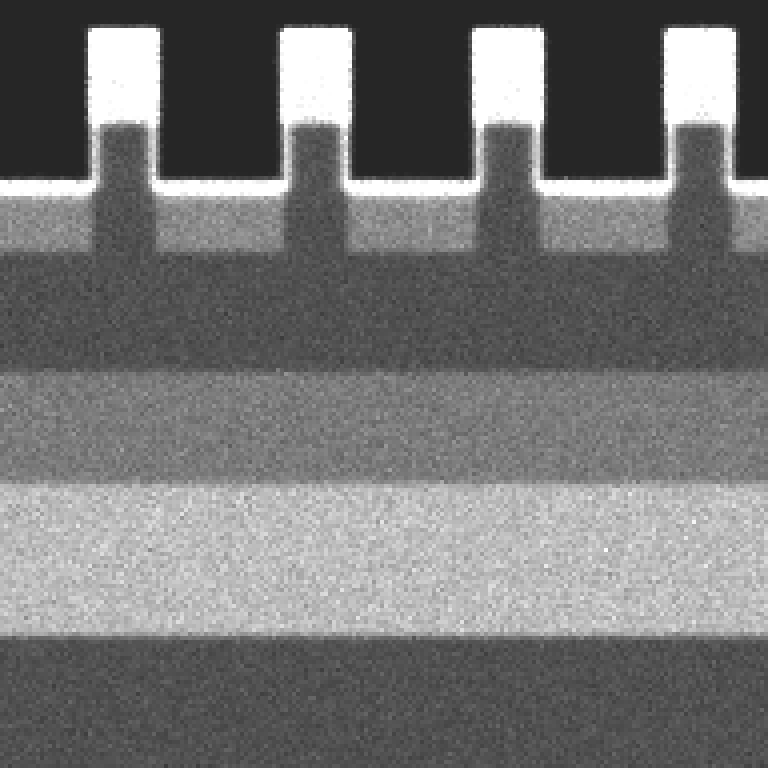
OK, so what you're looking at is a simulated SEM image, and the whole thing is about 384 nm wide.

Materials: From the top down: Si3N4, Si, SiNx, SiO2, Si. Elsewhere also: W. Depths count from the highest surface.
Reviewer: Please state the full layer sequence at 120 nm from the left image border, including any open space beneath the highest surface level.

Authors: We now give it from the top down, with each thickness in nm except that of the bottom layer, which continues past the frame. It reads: empty 76, Si3N4 34, Si 60, SiNx 56, SiO2 76, Si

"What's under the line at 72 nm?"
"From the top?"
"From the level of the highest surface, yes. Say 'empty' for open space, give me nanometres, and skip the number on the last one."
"W 46, Si 124, SiNx 56, SiO2 76, Si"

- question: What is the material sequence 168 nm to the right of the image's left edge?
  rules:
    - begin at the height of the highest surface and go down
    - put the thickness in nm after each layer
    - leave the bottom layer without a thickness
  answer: W 46, Si 124, SiNx 56, SiO2 76, Si